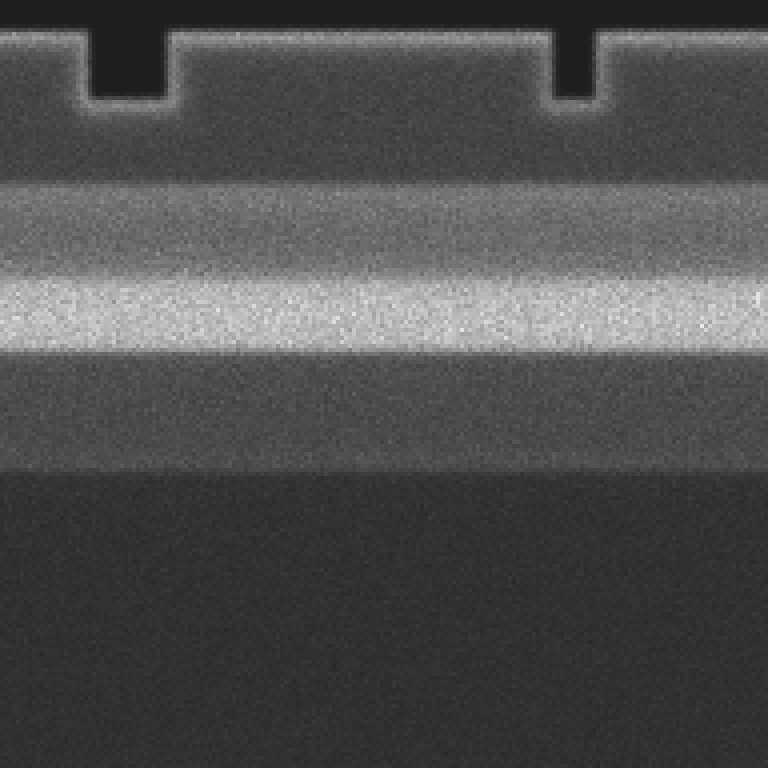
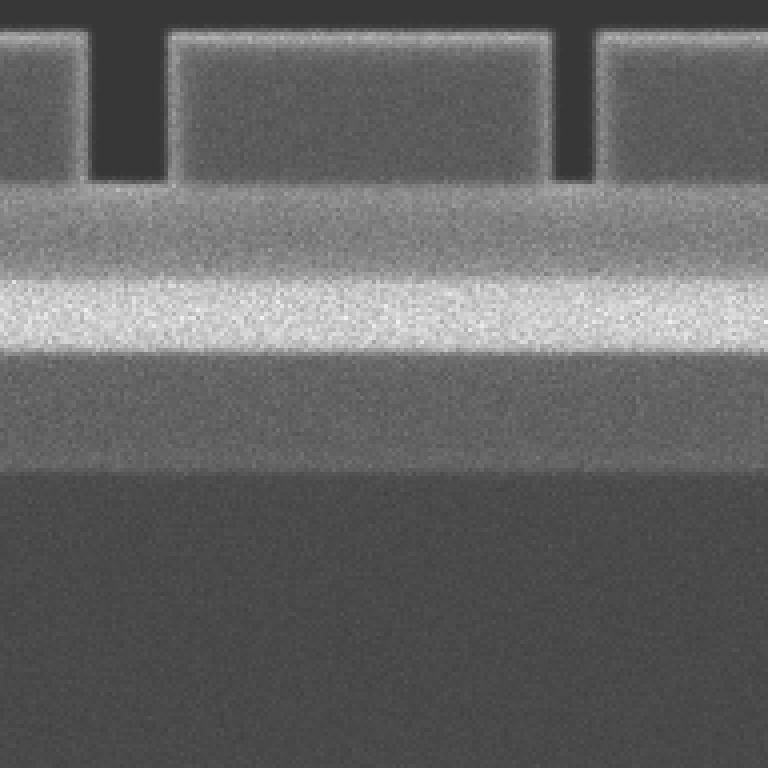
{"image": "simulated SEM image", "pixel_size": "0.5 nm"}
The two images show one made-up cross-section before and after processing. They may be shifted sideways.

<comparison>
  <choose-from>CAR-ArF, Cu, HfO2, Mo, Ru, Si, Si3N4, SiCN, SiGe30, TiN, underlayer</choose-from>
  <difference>underlayer removed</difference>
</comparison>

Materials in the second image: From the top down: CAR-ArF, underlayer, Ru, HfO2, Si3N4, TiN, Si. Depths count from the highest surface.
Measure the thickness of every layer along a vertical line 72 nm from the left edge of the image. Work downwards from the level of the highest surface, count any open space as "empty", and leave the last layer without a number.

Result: empty 76, Ru 48, HfO2 36, Si3N4 50, TiN 10, Si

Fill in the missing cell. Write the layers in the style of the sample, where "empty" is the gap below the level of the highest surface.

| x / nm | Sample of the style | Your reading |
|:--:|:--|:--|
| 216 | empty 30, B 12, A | CAR-ArF 34, underlayer 42, Ru 48, HfO2 36, Si3N4 50, TiN 10, Si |